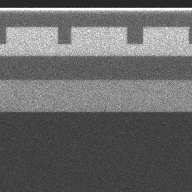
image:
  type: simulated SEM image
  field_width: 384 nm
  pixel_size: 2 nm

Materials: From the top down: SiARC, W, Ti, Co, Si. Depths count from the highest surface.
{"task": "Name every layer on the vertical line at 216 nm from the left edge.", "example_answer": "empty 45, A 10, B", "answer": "SiARC 38, W 58, Ti 48, Co 64, Si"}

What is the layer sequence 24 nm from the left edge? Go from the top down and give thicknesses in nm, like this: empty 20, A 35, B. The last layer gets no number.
SiARC 38, W 58, Ti 48, Co 64, Si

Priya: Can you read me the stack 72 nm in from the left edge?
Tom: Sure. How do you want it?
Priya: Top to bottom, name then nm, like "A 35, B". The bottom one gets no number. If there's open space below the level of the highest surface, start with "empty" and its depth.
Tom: SiARC 38, W 58, Ti 48, Co 64, Si